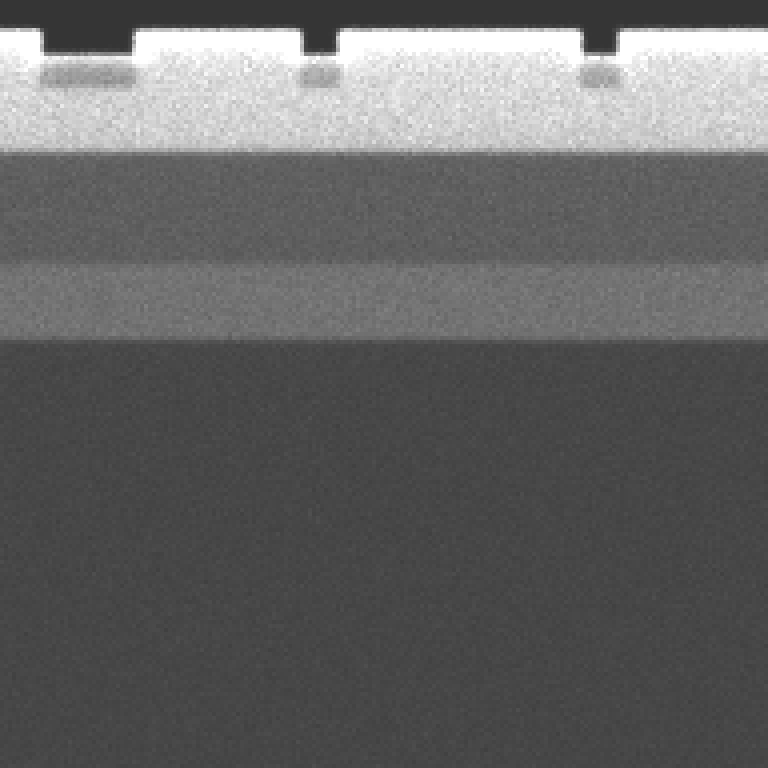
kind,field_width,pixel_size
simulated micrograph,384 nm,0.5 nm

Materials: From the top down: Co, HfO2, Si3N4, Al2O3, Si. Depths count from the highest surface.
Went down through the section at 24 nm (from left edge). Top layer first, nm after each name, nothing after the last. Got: empty 12, Co 16, HfO2 32, Si3N4 56, Al2O3 38, Si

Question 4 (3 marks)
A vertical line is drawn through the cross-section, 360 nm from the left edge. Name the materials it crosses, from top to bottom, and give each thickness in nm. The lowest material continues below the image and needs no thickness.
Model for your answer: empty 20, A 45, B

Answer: HfO2 60, Si3N4 56, Al2O3 38, Si